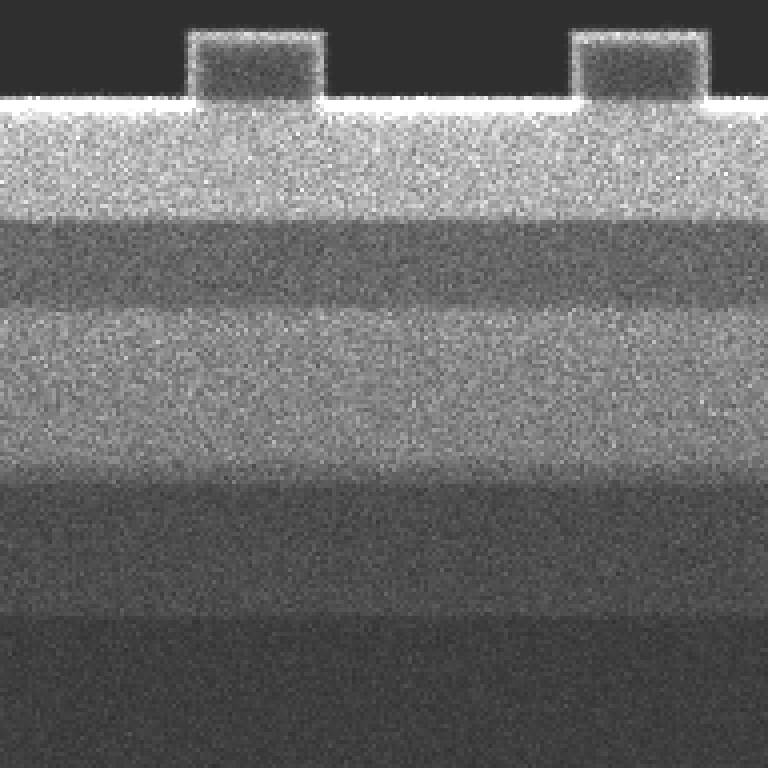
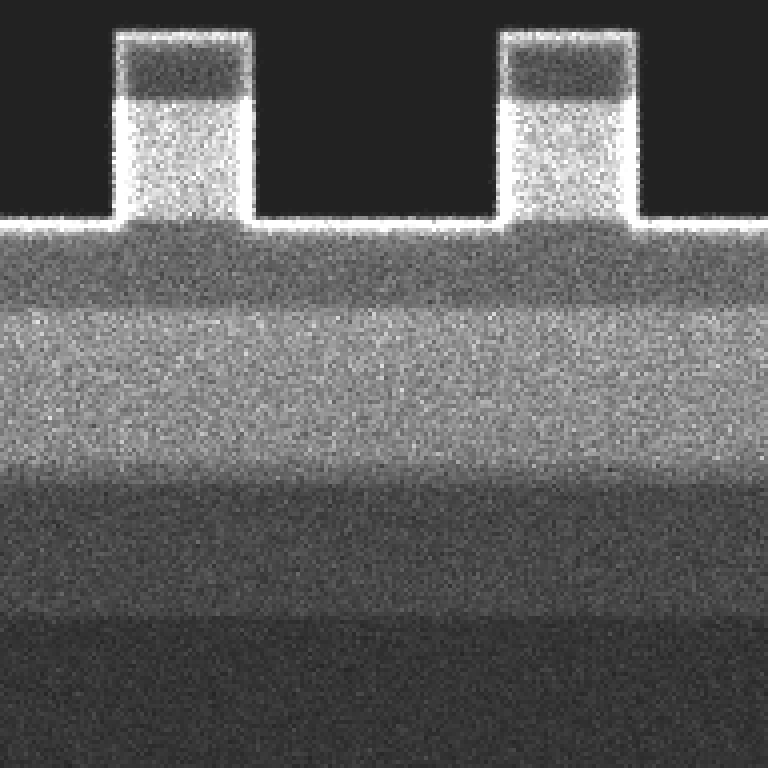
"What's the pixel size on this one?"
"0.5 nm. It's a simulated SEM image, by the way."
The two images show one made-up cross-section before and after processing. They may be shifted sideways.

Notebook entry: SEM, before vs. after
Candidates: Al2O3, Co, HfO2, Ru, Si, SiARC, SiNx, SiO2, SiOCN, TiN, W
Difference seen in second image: HfO2 removed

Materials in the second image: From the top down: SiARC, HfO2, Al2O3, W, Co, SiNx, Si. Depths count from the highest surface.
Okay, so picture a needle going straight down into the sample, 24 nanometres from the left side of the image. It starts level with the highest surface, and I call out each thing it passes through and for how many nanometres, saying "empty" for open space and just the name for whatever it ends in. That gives empty 94, Al2O3 44, W 78, Co 10, SiNx 66, Si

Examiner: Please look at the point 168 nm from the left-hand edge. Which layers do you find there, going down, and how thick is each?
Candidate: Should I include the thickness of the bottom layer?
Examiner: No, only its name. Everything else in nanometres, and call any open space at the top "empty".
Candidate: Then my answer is empty 94, Al2O3 44, W 78, Co 10, SiNx 66, Si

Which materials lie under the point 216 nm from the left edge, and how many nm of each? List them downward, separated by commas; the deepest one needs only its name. empty 94, Al2O3 44, W 78, Co 10, SiNx 66, Si